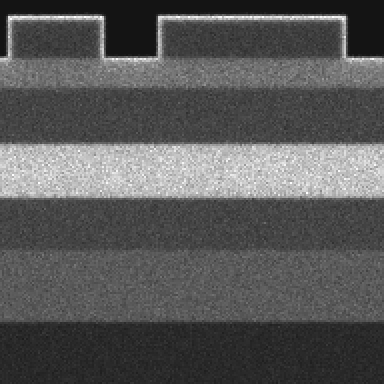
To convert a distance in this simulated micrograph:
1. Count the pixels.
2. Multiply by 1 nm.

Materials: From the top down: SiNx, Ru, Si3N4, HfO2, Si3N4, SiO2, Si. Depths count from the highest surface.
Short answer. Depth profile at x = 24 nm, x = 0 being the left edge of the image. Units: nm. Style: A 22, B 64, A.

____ SiNx 42, Ru 30, Si3N4 56, HfO2 54, Si3N4 52, SiO2 72, Si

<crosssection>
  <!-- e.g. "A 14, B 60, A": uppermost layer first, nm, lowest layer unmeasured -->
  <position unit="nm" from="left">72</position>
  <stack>SiNx 42, Ru 30, Si3N4 56, HfO2 54, Si3N4 52, SiO2 72, Si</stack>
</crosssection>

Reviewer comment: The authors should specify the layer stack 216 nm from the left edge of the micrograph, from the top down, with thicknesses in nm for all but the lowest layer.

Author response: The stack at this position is SiNx 42, Ru 30, Si3N4 56, HfO2 54, Si3N4 52, SiO2 72, Si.